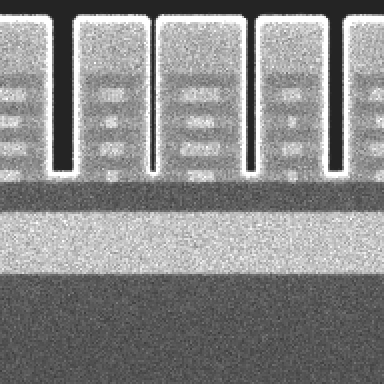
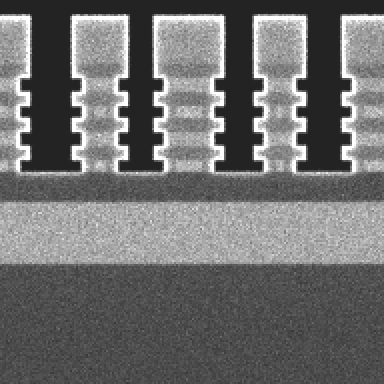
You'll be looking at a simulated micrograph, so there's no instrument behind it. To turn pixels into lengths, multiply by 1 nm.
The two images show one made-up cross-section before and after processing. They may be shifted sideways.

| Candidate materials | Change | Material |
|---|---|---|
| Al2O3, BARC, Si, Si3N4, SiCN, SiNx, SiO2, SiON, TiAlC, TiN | removed | Si3N4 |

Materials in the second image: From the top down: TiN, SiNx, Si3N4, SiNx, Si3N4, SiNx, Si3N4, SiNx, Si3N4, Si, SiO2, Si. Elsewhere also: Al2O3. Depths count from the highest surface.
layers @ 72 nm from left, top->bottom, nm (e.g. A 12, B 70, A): TiN 48, SiNx 14, empty 14, SiNx 14, empty 12, SiNx 14, empty 14, SiNx 14, empty 12, Si 30, SiO2 62, Si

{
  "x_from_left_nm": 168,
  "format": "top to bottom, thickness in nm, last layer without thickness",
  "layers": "TiN 48, SiNx 14, Si3N4 14, SiNx 14, Si3N4 12, SiNx 14, Si3N4 14, SiNx 14, Si3N4 12, Si 30, SiO2 62, Si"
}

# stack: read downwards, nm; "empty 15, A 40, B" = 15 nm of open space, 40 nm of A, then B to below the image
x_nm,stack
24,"TiN 48, SiNx 14, empty 14, SiNx 14, empty 12, SiNx 14, empty 14, SiNx 14, empty 12, Si 30, SiO2 62, Si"